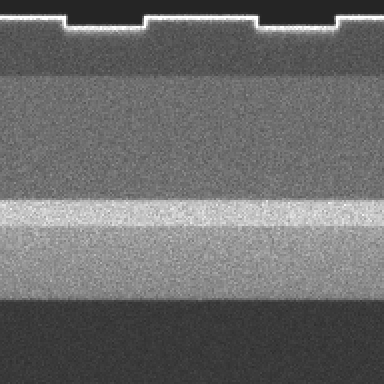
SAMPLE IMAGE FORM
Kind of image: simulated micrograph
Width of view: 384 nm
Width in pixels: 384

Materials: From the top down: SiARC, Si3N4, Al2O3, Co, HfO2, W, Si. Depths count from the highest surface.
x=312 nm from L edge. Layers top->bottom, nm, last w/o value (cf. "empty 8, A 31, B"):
empty 10, SiARC 16, Si3N4 34, Al2O3 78, Co 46, HfO2 26, W 74, Si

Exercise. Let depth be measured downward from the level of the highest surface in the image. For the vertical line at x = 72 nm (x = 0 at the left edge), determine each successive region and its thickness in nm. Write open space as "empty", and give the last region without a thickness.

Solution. empty 10, SiARC 16, Si3N4 34, Al2O3 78, Co 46, HfO2 26, W 74, Si